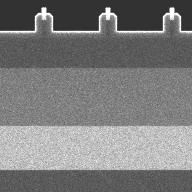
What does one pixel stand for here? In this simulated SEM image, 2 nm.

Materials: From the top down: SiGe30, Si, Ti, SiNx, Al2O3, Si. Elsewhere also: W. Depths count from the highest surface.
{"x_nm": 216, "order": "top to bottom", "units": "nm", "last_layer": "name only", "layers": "W 24, Si 96, Ti 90, SiNx 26, Al2O3 88, Si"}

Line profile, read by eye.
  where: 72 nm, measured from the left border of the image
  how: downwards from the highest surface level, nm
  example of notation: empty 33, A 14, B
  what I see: empty 14, SiGe30 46, Si 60, Ti 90, SiNx 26, Al2O3 88, Si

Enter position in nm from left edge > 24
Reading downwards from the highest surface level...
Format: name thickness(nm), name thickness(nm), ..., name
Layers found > empty 46, SiGe30 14, Si 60, Ti 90, SiNx 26, Al2O3 88, Si